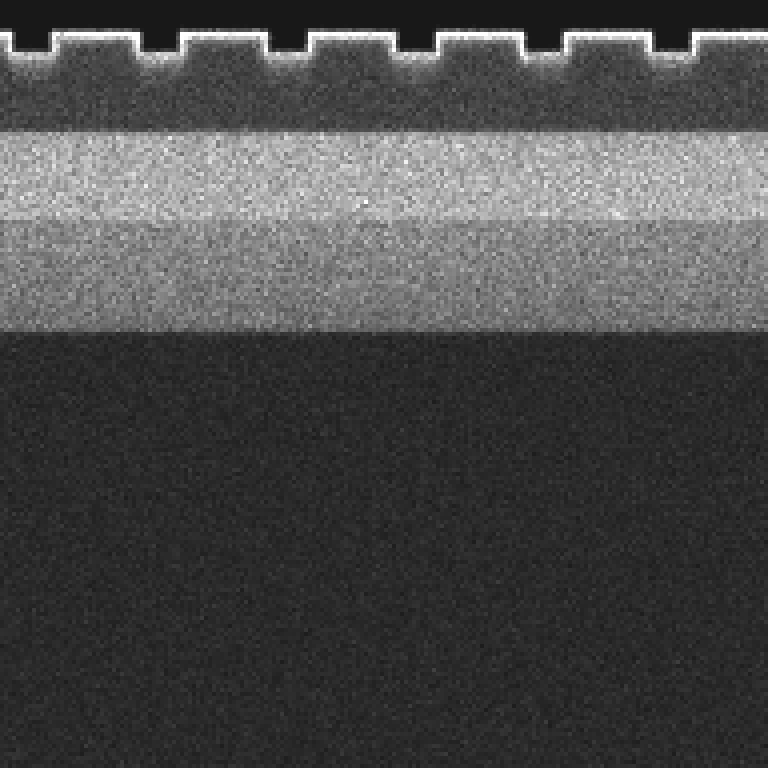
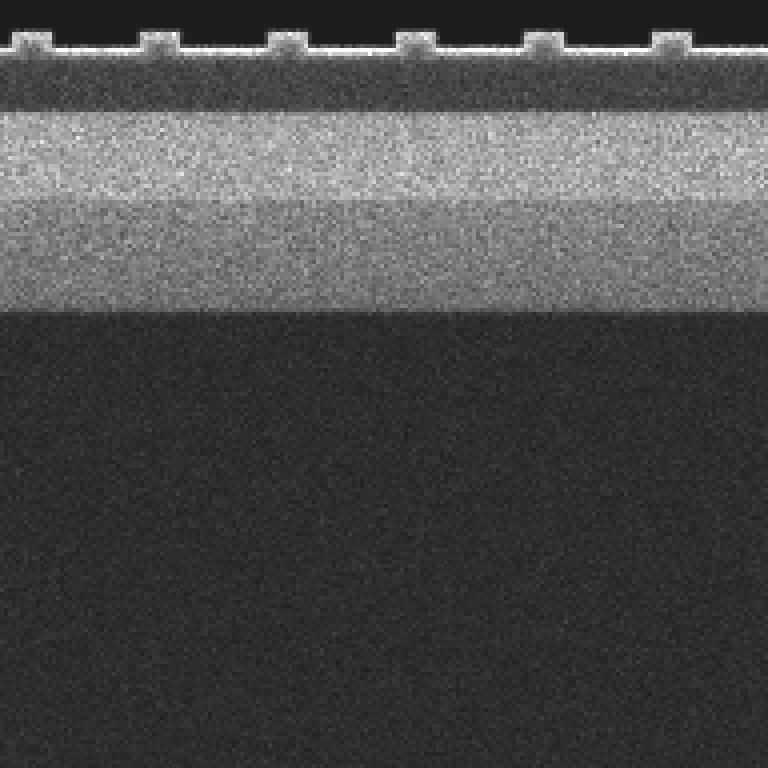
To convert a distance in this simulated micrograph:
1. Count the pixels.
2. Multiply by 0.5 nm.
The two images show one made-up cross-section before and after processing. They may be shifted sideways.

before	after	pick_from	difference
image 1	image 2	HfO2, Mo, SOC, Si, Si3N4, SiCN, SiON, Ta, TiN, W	Si3N4 removed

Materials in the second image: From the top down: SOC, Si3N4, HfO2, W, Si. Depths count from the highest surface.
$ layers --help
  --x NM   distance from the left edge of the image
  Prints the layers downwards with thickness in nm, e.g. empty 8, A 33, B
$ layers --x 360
empty 8, Si3N4 32, HfO2 44, W 56, Si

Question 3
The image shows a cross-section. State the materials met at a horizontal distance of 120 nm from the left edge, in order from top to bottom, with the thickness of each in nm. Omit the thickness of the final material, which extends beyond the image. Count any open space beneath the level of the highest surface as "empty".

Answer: empty 8, Si3N4 32, HfO2 44, W 56, Si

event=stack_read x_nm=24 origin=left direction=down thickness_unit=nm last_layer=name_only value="SOC 12, Si3N4 28, HfO2 44, W 56, Si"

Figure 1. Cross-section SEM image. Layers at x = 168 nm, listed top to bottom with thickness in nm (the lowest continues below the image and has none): empty 8, Si3N4 32, HfO2 44, W 56, Si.